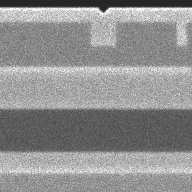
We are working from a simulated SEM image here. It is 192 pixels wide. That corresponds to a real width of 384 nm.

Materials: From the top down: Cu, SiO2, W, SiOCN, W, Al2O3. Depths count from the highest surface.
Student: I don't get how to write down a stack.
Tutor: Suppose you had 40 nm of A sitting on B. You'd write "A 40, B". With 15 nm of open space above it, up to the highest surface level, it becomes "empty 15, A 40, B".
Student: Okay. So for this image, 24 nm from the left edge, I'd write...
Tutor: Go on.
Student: Cu 28, SiO2 90, W 84, SiOCN 86, W 42, Al2O3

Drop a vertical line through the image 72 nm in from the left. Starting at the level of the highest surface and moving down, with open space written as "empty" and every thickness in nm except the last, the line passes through Cu 28, SiO2 90, W 84, SiOCN 86, W 42, Al2O3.